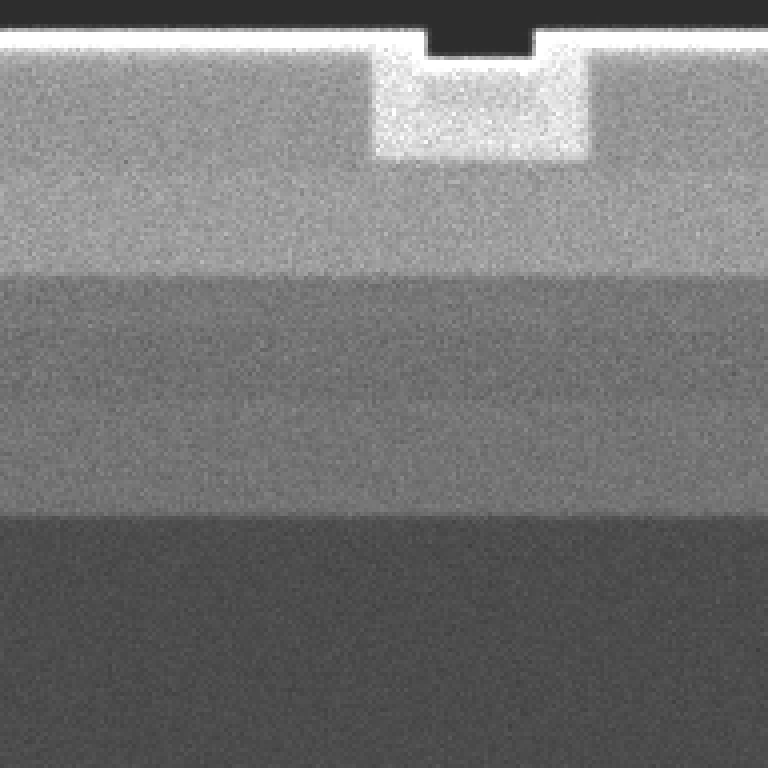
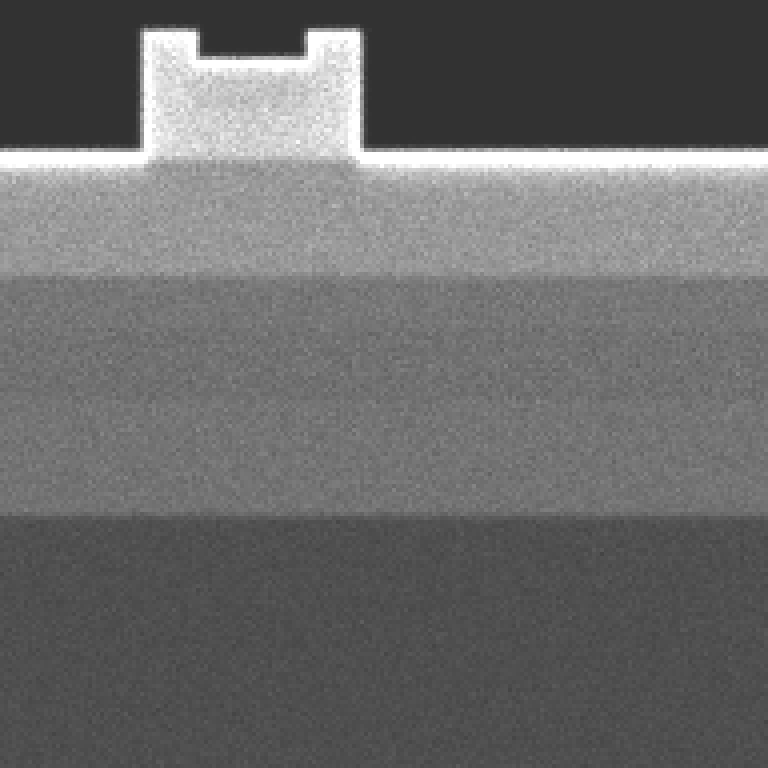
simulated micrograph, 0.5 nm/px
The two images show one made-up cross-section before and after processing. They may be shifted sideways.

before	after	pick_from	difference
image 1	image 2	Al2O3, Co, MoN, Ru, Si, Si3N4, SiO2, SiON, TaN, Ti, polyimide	SiO2 removed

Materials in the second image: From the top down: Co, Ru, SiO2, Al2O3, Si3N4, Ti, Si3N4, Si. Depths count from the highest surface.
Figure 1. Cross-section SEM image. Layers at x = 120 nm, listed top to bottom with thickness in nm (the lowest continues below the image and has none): empty 14, Co 24, Ru 26, SiO2 6, Al2O3 52, Si3N4 26, Ti 36, Si3N4 58, Si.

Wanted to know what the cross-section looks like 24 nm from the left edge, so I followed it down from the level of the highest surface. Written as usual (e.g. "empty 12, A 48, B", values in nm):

empty 60, SiO2 10, Al2O3 52, Si3N4 26, Ti 36, Si3N4 58, Si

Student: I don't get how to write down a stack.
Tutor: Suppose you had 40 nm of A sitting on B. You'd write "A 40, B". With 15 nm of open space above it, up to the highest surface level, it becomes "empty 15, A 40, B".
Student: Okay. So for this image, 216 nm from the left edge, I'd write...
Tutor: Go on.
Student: empty 60, SiO2 10, Al2O3 52, Si3N4 26, Ti 36, Si3N4 58, Si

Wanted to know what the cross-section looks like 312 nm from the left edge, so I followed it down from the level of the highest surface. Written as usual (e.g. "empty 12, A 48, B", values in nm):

empty 60, SiO2 10, Al2O3 52, Si3N4 26, Ti 36, Si3N4 58, Si